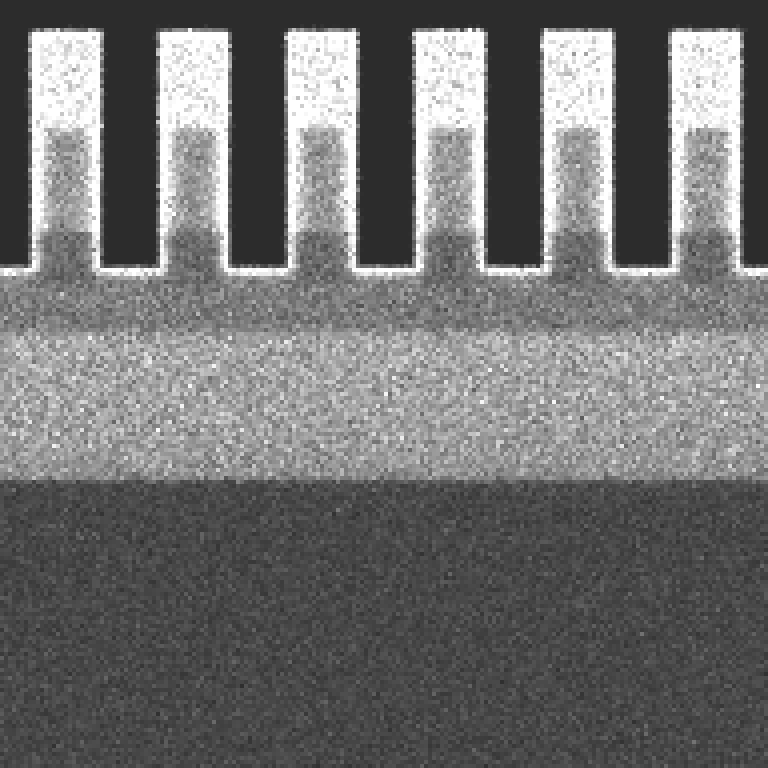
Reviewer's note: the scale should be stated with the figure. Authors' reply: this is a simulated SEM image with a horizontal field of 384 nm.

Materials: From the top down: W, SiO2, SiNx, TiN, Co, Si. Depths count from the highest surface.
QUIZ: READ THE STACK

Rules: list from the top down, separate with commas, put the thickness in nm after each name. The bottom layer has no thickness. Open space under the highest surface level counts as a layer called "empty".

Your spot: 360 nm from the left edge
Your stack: W 48, SiO2 52, SiNx 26, TiN 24, Co 74, Si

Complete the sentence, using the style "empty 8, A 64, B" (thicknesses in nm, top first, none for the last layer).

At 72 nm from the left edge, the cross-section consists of empty 118, SiNx 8, TiN 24, Co 74, Si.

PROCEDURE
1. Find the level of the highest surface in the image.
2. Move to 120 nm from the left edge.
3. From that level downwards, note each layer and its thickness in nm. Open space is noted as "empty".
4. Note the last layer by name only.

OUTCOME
empty 118, SiNx 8, TiN 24, Co 74, Si